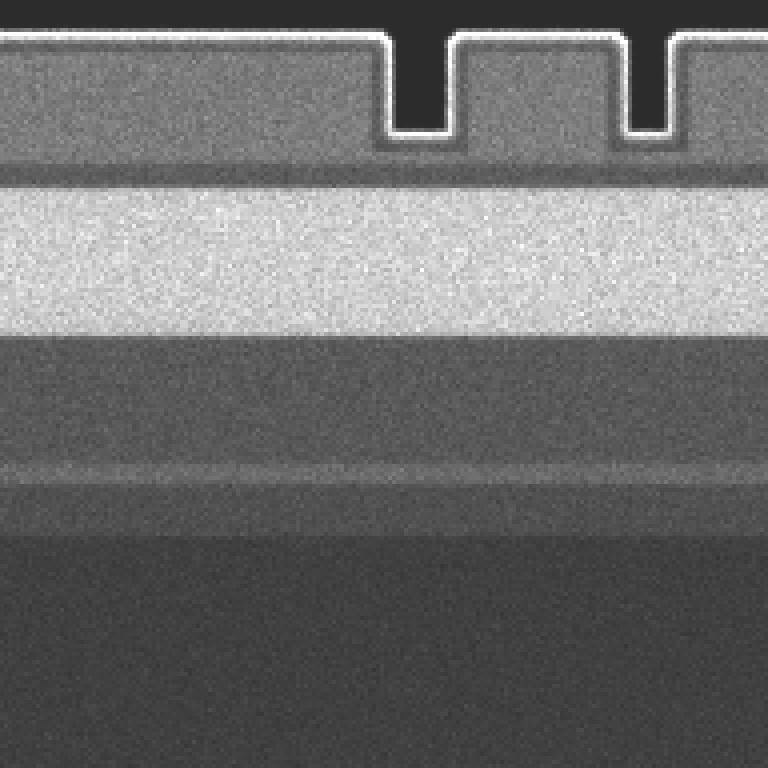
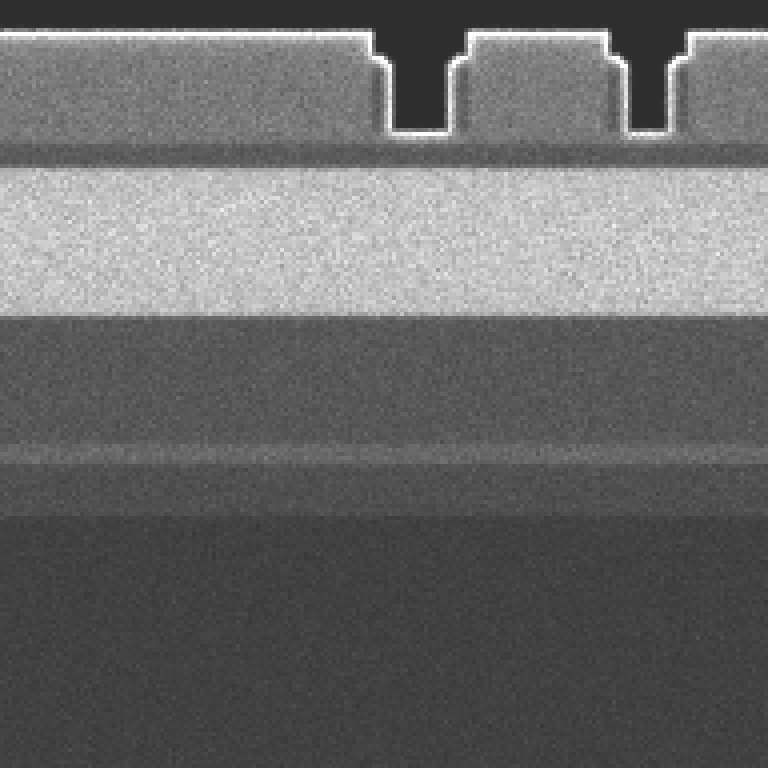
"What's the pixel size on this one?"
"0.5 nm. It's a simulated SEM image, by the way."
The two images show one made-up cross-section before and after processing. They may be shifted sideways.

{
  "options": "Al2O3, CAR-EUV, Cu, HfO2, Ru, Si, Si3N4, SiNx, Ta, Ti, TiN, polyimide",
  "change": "removed",
  "material": "SiNx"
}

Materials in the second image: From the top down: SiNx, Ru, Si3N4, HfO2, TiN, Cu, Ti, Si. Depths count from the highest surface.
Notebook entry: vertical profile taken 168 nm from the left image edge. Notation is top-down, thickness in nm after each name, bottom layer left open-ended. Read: Ru 56, Si3N4 12, HfO2 74, TiN 64, Cu 10, Ti 26, Si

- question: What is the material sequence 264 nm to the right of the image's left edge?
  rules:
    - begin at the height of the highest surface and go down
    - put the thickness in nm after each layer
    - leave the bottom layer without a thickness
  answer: Ru 56, Si3N4 12, HfO2 74, TiN 64, Cu 10, Ti 26, Si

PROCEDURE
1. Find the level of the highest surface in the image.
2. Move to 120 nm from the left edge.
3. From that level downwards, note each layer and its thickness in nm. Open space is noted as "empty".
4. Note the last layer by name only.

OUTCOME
Ru 56, Si3N4 12, HfO2 74, TiN 64, Cu 10, Ti 26, Si